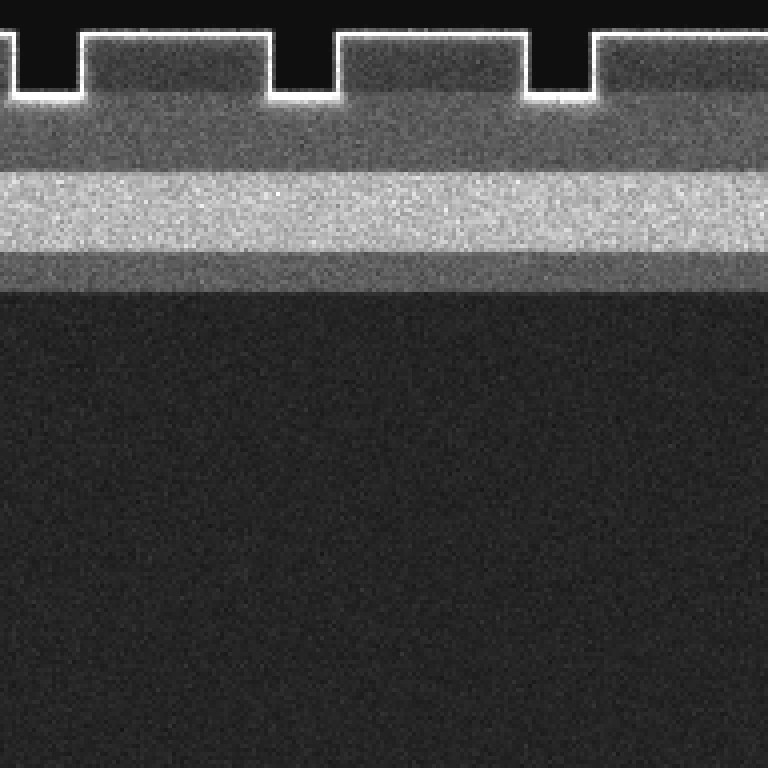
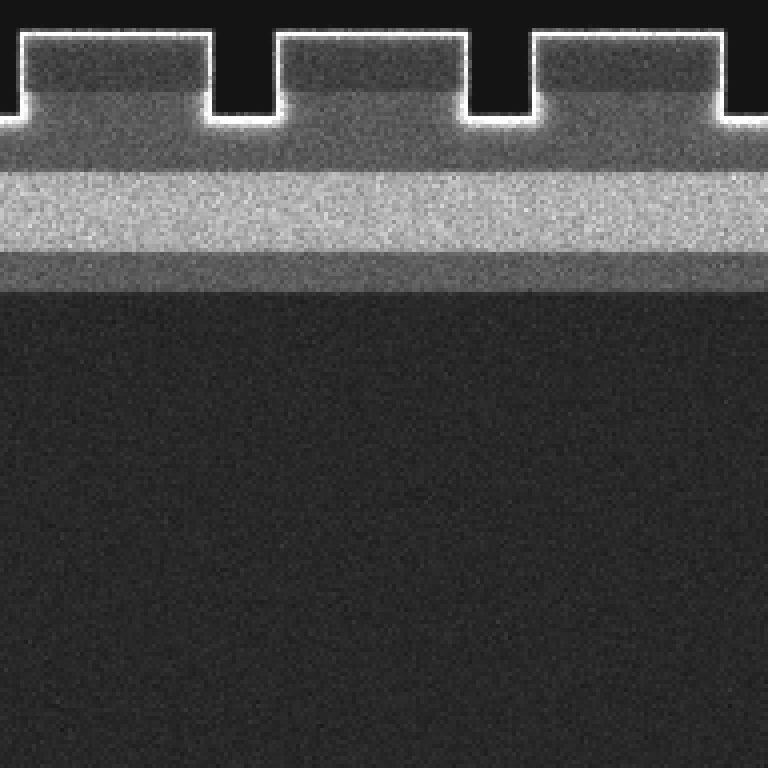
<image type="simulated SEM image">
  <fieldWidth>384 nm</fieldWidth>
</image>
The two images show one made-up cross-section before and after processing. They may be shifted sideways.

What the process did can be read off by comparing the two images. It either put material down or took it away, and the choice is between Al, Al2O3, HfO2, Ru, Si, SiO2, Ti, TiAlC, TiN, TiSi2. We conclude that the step removed SiO2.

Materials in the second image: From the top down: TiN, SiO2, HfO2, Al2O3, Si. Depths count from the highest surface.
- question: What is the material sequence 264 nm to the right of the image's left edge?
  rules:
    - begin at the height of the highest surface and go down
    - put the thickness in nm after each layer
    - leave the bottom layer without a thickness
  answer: empty 42, SiO2 28, HfO2 40, Al2O3 20, Si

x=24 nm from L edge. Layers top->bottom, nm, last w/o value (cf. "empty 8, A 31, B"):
TiN 30, SiO2 40, HfO2 40, Al2O3 20, Si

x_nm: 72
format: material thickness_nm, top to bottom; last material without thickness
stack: TiN 30, SiO2 40, HfO2 40, Al2O3 20, Si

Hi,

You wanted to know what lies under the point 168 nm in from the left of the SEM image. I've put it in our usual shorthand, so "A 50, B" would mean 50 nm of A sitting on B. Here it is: TiN 30, SiO2 40, HfO2 40, Al2O3 20, Si